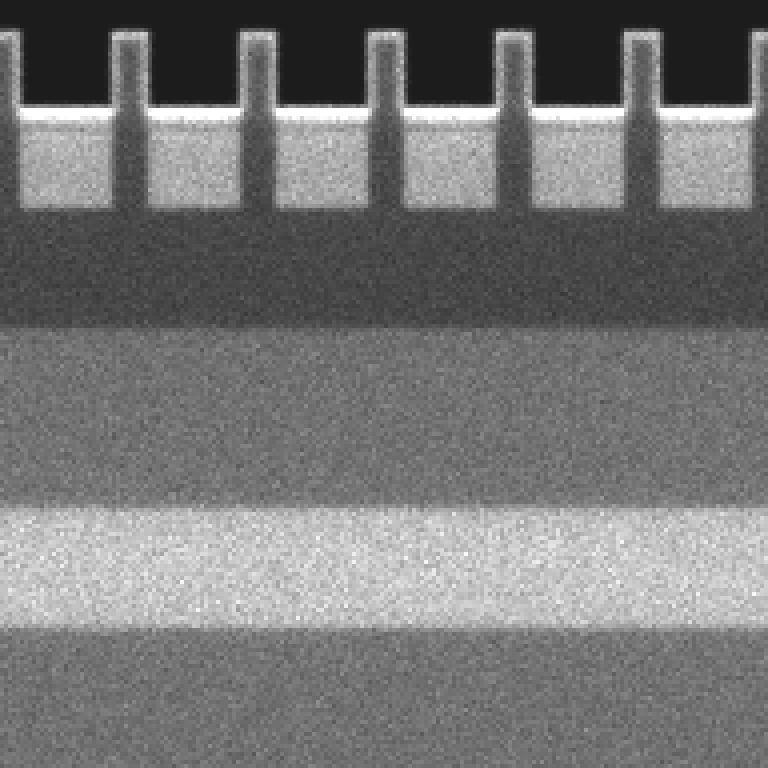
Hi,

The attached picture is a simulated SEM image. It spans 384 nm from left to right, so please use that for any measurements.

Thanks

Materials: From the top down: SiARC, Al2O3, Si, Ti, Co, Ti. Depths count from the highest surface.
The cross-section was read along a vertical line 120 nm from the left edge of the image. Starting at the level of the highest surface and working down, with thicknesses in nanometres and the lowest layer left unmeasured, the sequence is Si 148, Ti 90, Co 60, Ti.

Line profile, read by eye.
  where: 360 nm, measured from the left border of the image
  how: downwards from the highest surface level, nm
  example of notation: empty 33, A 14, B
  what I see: empty 38, SiARC 12, Al2O3 38, Si 60, Ti 90, Co 60, Ti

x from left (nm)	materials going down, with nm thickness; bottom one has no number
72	Si 148, Ti 90, Co 60, Ti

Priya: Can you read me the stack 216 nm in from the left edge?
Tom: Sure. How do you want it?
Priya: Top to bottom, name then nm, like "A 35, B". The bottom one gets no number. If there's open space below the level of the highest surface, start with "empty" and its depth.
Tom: empty 38, SiARC 12, Al2O3 38, Si 60, Ti 90, Co 60, Ti